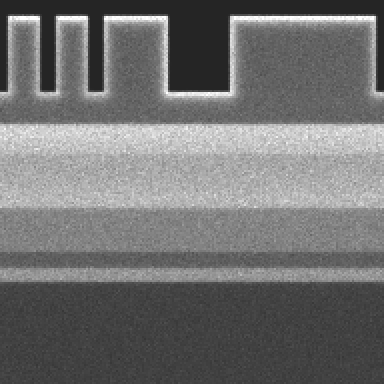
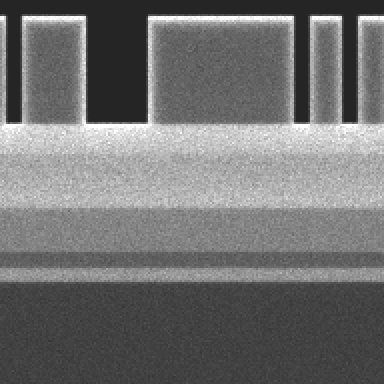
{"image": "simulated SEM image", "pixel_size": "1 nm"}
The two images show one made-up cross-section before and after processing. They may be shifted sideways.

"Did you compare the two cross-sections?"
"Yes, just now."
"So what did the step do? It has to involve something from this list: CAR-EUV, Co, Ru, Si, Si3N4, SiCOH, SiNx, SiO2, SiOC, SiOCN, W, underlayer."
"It removed underlayer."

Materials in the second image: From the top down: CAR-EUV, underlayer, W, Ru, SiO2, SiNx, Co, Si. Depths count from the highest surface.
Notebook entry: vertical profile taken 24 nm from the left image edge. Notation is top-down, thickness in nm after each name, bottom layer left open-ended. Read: CAR-EUV 76, underlayer 32, W 30, Ru 54, SiO2 44, SiNx 16, Co 14, Si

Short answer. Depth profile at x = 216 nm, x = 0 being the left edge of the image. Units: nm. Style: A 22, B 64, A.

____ CAR-EUV 76, underlayer 32, W 30, Ru 54, SiO2 44, SiNx 16, Co 14, Si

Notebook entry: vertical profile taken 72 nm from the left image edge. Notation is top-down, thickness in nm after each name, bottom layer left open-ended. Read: CAR-EUV 76, underlayer 32, W 30, Ru 54, SiO2 44, SiNx 16, Co 14, Si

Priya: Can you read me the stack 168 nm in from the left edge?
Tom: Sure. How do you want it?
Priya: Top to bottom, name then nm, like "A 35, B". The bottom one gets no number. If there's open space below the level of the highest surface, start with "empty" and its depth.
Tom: CAR-EUV 76, underlayer 32, W 30, Ru 54, SiO2 44, SiNx 16, Co 14, Si